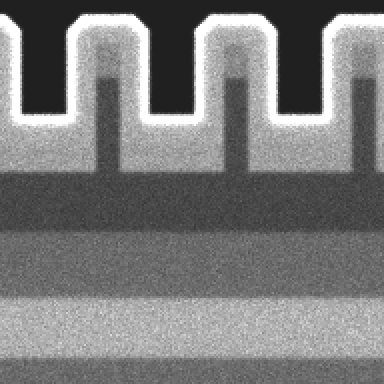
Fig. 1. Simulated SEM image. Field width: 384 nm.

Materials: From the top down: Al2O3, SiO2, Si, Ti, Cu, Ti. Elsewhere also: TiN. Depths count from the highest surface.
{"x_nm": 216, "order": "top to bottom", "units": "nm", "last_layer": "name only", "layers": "Al2O3 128, SiO2 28, Si 60, Ti 66, Cu 60, Ti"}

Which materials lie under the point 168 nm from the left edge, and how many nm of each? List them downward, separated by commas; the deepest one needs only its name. empty 100, Al2O3 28, SiO2 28, Si 60, Ti 66, Cu 60, Ti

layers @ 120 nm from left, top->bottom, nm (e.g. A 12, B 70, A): Al2O3 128, SiO2 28, Si 60, Ti 66, Cu 60, Ti